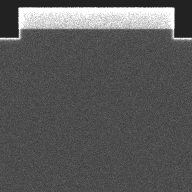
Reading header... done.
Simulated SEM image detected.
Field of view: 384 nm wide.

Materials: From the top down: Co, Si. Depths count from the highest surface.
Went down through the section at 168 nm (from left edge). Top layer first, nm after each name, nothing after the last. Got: Co 42, Si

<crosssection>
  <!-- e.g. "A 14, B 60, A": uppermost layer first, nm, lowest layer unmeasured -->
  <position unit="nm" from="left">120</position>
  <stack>Co 42, Si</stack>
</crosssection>